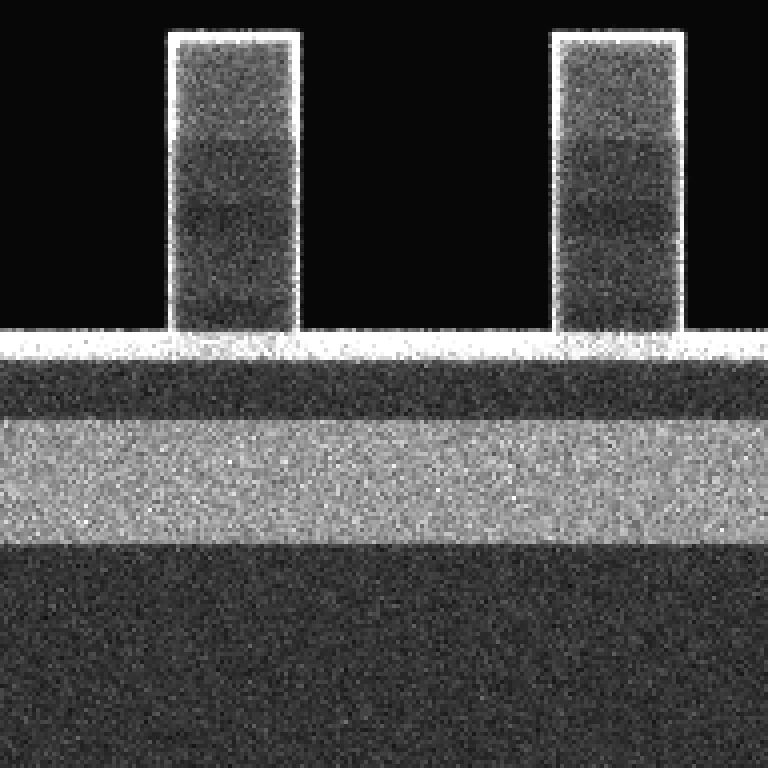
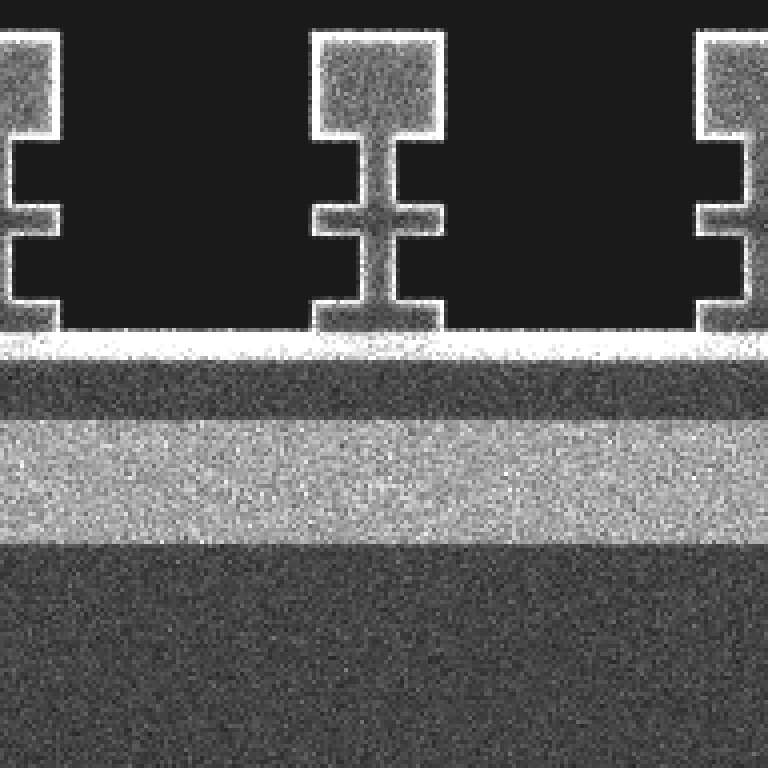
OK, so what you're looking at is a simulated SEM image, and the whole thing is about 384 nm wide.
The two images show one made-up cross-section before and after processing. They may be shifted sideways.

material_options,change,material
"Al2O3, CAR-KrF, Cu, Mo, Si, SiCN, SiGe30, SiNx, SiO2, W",removed,SiGe30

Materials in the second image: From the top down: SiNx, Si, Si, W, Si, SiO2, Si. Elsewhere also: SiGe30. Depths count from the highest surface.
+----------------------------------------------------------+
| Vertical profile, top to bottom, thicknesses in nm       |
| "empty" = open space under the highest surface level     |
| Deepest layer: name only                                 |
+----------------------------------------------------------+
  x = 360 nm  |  SiNx 54, empty 32, Si 16, empty 32, Si 16, W 14, Si 30, SiO2 62, Si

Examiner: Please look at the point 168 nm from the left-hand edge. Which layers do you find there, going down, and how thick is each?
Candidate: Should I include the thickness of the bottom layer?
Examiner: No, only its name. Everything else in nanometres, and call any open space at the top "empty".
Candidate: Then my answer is SiNx 54, empty 32, Si 16, empty 32, Si 16, W 14, Si 30, SiO2 62, Si